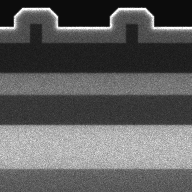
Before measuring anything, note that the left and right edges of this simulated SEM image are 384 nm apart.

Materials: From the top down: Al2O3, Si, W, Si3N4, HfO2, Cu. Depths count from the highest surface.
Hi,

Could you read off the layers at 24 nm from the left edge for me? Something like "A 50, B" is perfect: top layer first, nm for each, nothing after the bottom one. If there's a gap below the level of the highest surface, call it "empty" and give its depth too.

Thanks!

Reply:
empty 38, Al2O3 32, Si 60, W 44, Si3N4 60, HfO2 88, Cu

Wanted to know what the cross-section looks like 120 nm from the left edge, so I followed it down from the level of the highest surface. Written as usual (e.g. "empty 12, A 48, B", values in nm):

empty 38, Al2O3 32, Si 60, W 44, Si3N4 60, HfO2 88, Cu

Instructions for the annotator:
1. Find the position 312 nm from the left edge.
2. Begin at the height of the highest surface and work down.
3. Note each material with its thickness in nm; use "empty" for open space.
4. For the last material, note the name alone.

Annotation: empty 38, Al2O3 32, Si 60, W 44, Si3N4 60, HfO2 88, Cu